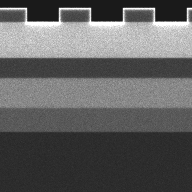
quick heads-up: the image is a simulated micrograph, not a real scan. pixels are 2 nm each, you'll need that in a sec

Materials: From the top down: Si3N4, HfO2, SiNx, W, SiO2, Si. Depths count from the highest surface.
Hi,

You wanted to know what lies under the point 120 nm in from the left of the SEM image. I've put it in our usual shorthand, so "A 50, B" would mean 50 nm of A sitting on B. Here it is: Si3N4 28, HfO2 72, SiNx 40, W 60, SiO2 48, Si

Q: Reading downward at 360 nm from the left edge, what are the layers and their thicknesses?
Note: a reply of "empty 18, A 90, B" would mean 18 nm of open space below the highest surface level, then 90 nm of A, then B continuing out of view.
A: empty 28, HfO2 72, SiNx 40, W 60, SiO2 48, Si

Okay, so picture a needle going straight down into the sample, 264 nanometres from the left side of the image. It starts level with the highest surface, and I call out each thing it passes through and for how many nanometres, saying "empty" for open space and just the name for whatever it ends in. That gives Si3N4 28, HfO2 72, SiNx 40, W 60, SiO2 48, Si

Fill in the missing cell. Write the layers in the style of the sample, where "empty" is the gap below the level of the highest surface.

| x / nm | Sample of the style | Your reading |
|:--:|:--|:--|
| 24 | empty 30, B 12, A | Si3N4 28, HfO2 72, SiNx 40, W 60, SiO2 48, Si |